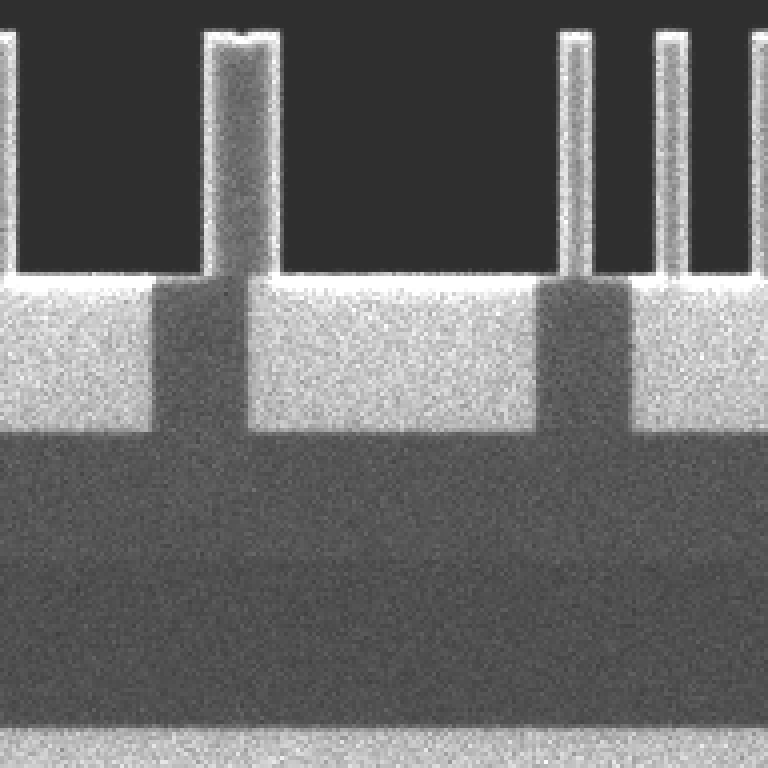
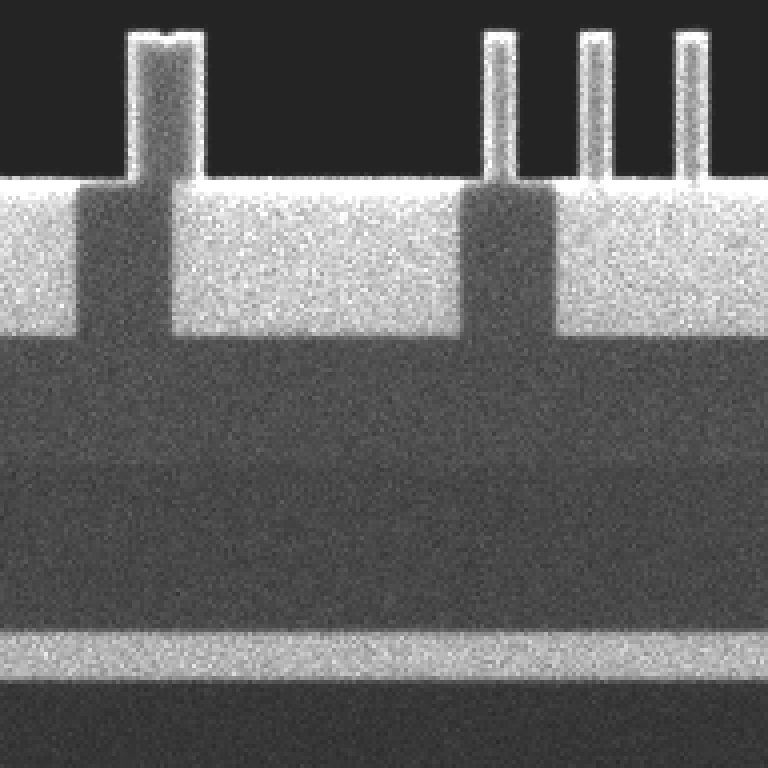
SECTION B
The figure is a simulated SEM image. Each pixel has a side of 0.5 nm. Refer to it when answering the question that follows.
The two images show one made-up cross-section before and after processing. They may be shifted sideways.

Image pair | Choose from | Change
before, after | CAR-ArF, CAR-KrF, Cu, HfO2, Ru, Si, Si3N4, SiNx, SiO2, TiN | SiO2 (removed)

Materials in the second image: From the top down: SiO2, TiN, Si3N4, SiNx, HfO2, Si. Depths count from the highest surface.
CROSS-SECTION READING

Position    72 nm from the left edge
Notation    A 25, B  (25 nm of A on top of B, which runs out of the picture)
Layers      SiO2 74, TiN 116, Si3N4 26, SiNx 84, HfO2 24, Si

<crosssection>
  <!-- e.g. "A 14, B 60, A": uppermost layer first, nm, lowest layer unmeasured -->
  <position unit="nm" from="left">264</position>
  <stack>empty 74, TiN 78, Si3N4 64, SiNx 84, HfO2 24, Si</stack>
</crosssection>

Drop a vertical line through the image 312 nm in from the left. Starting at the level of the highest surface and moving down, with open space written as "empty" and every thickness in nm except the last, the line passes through empty 74, HfO2 78, Si3N4 64, SiNx 84, HfO2 24, Si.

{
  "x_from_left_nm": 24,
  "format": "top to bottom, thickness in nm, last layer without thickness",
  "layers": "empty 74, HfO2 78, Si3N4 64, SiNx 84, HfO2 24, Si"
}